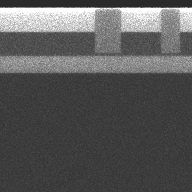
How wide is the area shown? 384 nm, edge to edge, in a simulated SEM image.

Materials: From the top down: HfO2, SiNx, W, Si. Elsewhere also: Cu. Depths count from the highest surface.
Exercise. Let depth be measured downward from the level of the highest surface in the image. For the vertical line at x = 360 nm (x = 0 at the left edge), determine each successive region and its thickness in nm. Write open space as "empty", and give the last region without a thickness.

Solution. HfO2 48, SiNx 48, W 34, Si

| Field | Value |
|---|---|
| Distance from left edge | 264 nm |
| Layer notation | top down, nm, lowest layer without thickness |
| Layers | HfO2 48, SiNx 48, W 34, Si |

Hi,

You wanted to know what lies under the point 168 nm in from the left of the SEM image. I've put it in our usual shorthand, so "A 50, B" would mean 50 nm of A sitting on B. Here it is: HfO2 48, SiNx 48, W 34, Si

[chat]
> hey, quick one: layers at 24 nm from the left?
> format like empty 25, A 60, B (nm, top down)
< HfO2 48, SiNx 48, W 34, Si